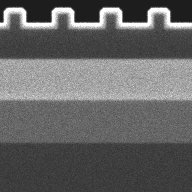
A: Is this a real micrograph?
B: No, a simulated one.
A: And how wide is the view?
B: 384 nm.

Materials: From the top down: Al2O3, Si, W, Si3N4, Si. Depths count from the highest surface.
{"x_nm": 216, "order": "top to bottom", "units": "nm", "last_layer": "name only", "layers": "Al2O3 12, Si 90, W 82, Si3N4 86, Si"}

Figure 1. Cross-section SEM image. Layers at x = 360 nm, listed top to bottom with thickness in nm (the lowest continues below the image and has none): empty 30, Al2O3 12, Si 60, W 82, Si3N4 86, Si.